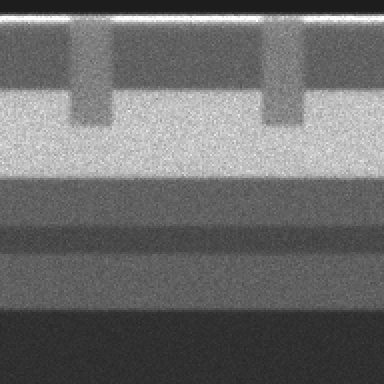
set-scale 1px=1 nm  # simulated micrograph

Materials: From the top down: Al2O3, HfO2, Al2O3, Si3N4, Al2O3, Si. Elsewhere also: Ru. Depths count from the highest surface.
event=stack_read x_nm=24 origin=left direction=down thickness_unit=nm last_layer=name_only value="Al2O3 74, HfO2 88, Al2O3 48, Si3N4 28, Al2O3 56, Si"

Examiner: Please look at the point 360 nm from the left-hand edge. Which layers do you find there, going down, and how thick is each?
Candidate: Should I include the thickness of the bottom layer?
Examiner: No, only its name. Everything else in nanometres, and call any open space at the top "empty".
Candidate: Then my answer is Al2O3 74, HfO2 88, Al2O3 48, Si3N4 28, Al2O3 56, Si